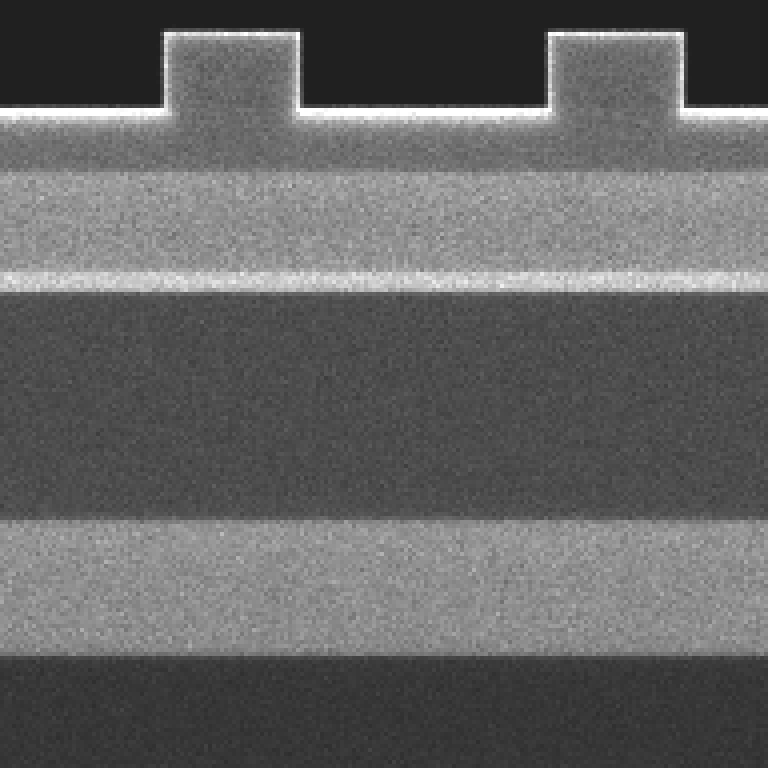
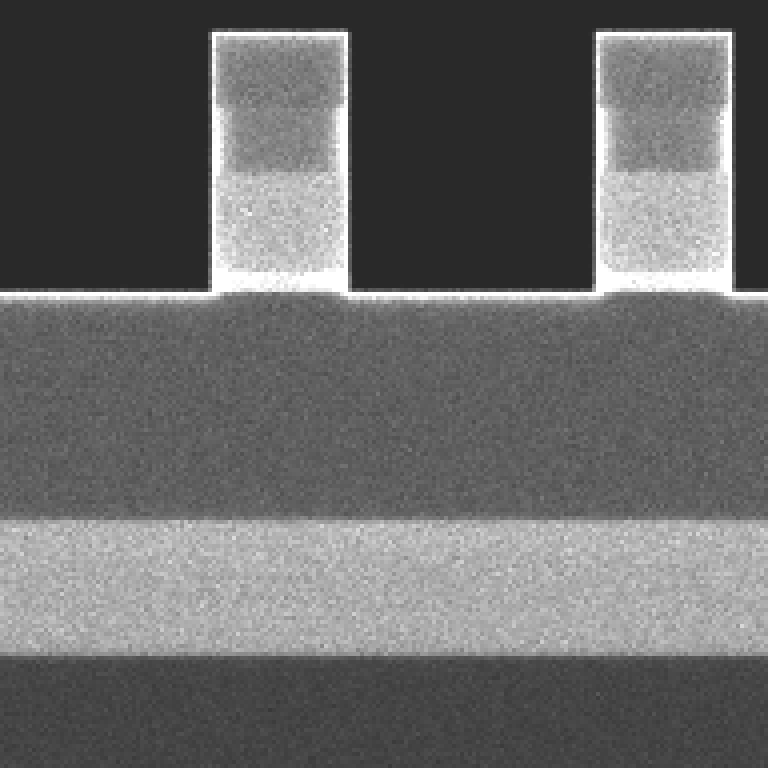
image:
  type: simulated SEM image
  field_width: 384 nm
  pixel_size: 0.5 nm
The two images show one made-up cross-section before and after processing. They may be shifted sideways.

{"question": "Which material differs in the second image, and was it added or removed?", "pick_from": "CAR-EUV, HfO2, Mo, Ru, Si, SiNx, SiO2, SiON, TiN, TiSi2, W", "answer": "HfO2 and Ru and SiO2, removed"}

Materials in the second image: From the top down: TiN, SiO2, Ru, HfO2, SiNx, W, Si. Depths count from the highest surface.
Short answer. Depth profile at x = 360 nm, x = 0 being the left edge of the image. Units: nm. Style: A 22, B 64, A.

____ TiN 38, SiO2 32, Ru 50, HfO2 10, SiNx 114, W 68, Si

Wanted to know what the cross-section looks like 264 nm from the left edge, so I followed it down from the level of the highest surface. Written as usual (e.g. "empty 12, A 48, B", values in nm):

empty 130, SiNx 114, W 68, Si